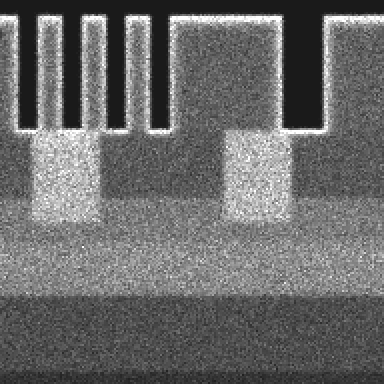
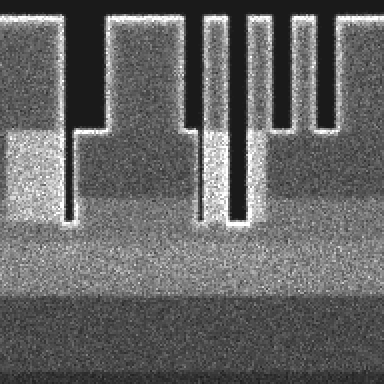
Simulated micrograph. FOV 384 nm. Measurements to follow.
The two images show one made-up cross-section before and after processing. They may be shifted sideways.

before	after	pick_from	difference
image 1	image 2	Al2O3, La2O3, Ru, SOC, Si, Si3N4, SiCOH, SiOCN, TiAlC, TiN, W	W removed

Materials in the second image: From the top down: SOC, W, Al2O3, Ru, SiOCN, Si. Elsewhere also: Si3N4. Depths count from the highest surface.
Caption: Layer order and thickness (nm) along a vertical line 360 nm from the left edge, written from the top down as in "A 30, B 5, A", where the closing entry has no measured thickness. SOC 114, Si3N4 68, Al2O3 44, Ru 54, SiOCN 76, Si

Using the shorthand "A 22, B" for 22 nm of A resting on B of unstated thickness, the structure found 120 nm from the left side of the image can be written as SOC 114, Si3N4 68, Al2O3 44, Ru 54, SiOCN 76, Si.